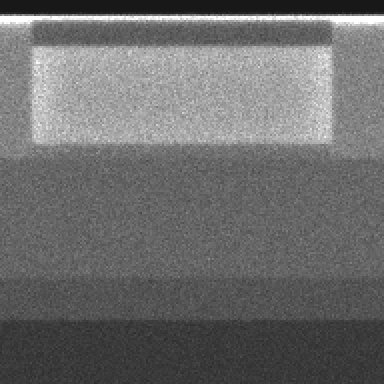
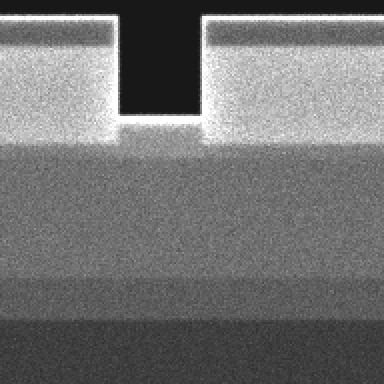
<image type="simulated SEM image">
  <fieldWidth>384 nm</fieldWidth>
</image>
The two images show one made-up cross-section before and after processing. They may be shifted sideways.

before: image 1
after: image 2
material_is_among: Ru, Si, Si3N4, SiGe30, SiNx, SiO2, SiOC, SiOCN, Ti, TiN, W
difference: SiO2, removed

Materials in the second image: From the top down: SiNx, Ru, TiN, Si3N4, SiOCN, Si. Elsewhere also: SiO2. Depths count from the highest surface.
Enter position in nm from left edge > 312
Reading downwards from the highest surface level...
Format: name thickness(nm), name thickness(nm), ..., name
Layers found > SiNx 30, Ru 98, TiN 14, Si3N4 120, SiOCN 42, Si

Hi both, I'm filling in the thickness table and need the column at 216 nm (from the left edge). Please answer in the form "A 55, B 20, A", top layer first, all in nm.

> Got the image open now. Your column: SiNx 30, Ru 98, TiN 14, Si3N4 120, SiOCN 42, Si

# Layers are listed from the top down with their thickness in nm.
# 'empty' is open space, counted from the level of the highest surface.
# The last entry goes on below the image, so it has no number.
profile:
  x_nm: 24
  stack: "SiNx 30, Ru 98, TiN 14, Si3N4 120, SiOCN 42, Si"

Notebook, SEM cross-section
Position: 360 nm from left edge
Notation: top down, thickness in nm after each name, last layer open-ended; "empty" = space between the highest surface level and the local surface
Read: SiNx 30, Ru 98, TiN 14, Si3N4 120, SiOCN 42, Si